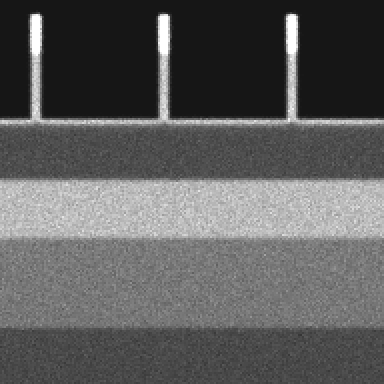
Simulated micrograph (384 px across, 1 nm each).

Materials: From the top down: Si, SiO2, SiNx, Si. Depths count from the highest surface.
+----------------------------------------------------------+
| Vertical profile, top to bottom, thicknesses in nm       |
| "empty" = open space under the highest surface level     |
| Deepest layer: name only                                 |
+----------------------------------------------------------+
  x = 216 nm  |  empty 104, Si 60, SiO2 58, SiNx 90, Si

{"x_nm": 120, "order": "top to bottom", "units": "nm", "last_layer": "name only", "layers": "empty 104, Si 60, SiO2 58, SiNx 90, Si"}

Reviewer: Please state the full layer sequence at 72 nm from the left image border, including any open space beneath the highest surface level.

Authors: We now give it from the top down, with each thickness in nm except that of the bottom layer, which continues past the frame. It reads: empty 104, Si 60, SiO2 58, SiNx 90, Si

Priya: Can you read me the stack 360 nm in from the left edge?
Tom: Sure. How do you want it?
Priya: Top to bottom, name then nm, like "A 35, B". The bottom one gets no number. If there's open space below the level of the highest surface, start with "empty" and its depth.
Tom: empty 104, Si 60, SiO2 58, SiNx 90, Si